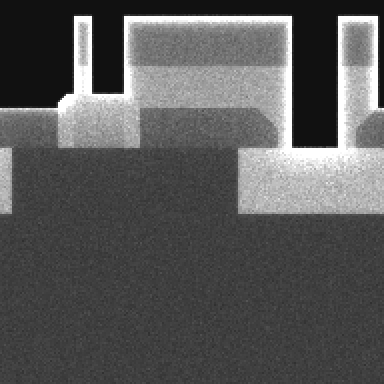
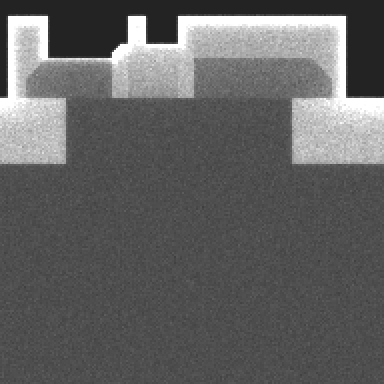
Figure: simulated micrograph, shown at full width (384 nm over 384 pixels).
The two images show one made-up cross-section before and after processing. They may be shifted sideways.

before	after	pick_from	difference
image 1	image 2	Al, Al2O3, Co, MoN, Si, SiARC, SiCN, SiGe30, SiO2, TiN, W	SiARC removed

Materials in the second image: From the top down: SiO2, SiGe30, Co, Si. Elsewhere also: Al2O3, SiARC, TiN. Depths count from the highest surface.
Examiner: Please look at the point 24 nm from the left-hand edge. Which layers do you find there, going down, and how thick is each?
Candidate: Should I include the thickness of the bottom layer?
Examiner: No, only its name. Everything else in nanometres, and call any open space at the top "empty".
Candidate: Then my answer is SiO2 82, Co 66, Si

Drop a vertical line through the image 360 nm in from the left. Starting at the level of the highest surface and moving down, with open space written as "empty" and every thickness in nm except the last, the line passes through empty 82, Co 66, Si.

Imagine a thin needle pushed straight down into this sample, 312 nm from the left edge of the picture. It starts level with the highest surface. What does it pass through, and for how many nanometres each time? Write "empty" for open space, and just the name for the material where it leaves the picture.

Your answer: SiO2 44, SiGe30 38, Co 66, Si